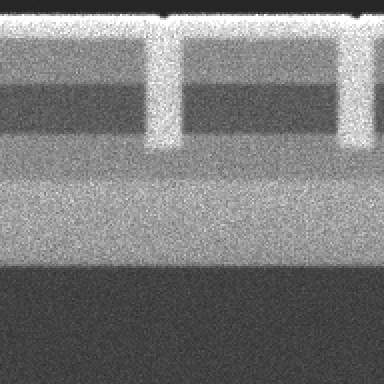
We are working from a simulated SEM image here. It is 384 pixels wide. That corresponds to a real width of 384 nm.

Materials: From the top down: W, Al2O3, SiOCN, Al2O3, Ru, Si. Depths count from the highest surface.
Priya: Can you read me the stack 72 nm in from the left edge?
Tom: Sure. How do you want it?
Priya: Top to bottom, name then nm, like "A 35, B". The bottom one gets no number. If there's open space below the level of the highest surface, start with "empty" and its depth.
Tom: W 22, Al2O3 46, SiOCN 50, Al2O3 46, Ru 86, Si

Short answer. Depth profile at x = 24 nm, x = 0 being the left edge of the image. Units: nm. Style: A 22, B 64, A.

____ W 22, Al2O3 46, SiOCN 50, Al2O3 46, Ru 86, Si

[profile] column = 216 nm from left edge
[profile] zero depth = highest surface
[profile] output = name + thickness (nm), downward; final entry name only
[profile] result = W 22, Al2O3 46, SiOCN 50, Al2O3 46, Ru 86, Si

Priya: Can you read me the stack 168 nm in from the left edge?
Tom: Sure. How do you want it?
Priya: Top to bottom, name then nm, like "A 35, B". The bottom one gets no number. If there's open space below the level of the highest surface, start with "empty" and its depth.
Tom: empty 2, W 130, Al2O3 32, Ru 86, Si